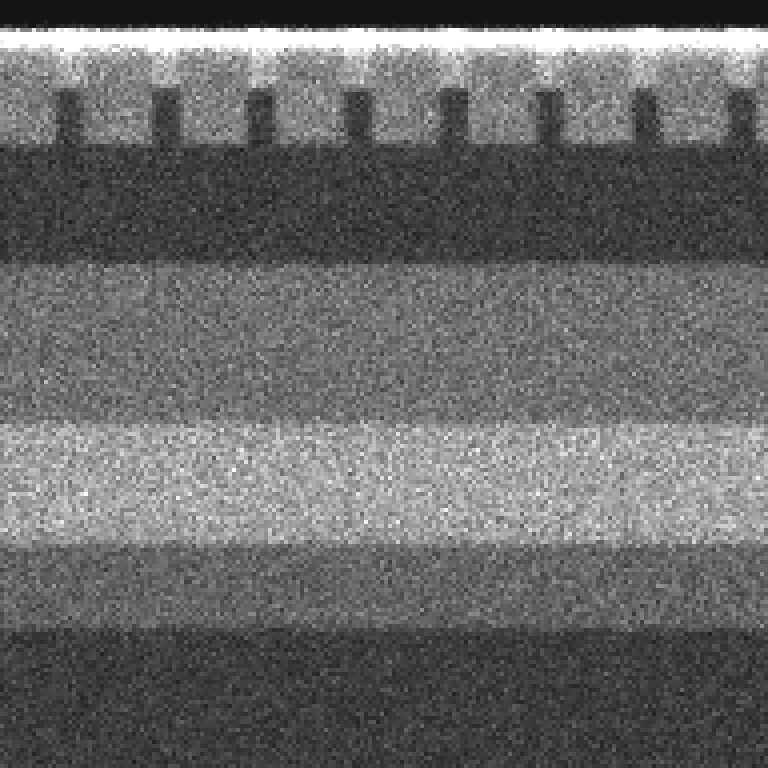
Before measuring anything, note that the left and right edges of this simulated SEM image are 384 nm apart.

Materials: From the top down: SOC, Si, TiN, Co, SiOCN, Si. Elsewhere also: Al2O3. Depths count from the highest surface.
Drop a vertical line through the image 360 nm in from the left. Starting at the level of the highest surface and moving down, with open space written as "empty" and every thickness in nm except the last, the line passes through SOC 56, Si 60, TiN 80, Co 60, SiOCN 42, Si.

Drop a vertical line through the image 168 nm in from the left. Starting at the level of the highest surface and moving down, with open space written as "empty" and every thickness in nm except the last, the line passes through SOC 56, Si 60, TiN 80, Co 60, SiOCN 42, Si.